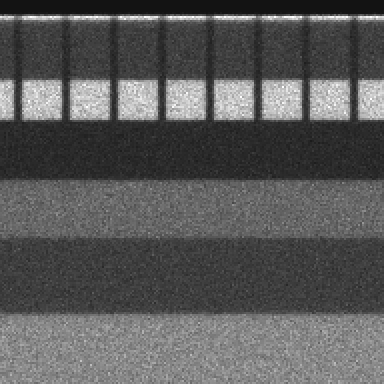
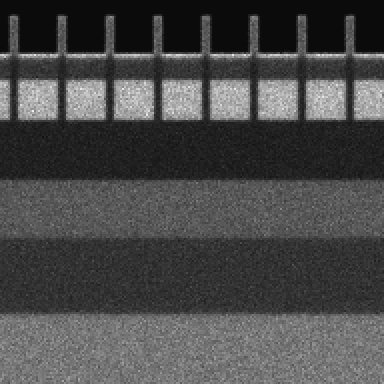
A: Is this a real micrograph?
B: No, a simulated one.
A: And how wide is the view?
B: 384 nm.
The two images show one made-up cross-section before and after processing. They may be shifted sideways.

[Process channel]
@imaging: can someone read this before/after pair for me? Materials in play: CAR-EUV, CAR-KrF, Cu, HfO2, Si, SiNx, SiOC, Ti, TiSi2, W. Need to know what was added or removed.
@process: SiNx removed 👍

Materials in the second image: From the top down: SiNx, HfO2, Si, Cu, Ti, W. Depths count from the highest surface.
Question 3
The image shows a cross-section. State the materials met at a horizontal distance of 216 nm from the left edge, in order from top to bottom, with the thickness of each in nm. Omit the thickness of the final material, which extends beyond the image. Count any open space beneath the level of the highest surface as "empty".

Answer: empty 38, SiNx 26, HfO2 40, Si 60, Cu 58, Ti 76, W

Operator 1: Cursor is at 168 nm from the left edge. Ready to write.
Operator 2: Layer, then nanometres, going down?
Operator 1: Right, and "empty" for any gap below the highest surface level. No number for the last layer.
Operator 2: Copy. empty 38, SiNx 26, HfO2 40, Si 60, Cu 58, Ti 76, W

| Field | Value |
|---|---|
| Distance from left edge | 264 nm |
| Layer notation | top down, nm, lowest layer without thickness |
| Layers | empty 38, SiNx 26, HfO2 40, Si 60, Cu 58, Ti 76, W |